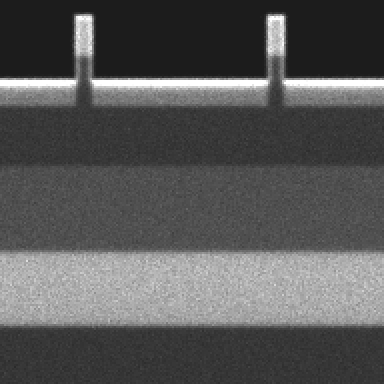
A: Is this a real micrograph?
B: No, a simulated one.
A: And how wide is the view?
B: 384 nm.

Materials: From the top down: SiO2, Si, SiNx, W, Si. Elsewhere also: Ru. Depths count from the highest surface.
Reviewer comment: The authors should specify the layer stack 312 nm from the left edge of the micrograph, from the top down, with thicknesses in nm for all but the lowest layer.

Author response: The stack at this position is empty 64, SiO2 26, Si 60, SiNx 86, W 74, Si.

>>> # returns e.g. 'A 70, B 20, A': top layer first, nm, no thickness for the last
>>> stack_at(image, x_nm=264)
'empty 64, SiO2 26, Si 60, SiNx 86, W 74, Si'